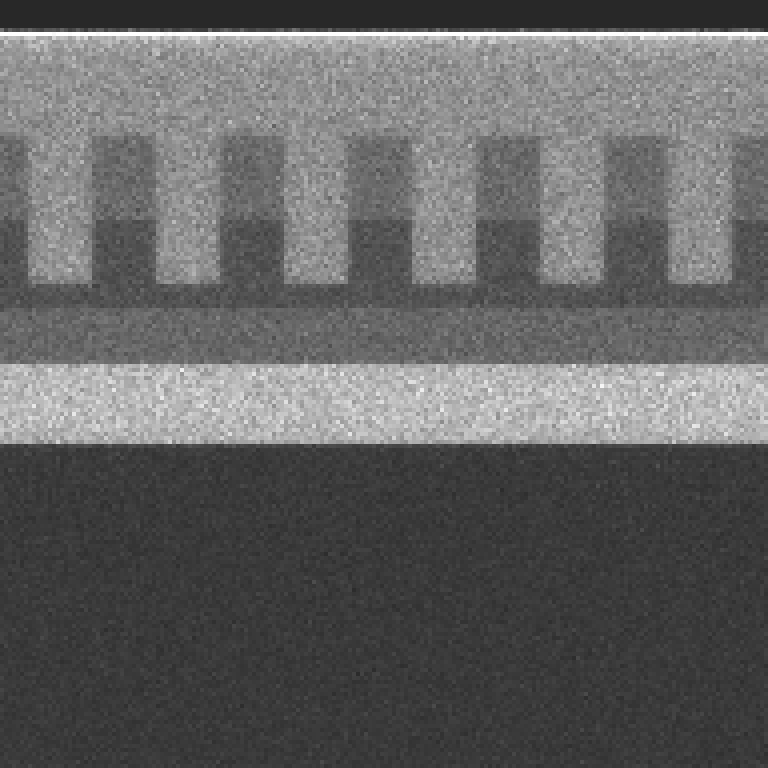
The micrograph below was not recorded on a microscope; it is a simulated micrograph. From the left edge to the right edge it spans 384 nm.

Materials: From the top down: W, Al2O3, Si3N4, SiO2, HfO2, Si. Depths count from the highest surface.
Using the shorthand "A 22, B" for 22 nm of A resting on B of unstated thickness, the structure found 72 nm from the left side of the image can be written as W 52, Al2O3 42, Si3N4 44, SiO2 28, HfO2 40, Si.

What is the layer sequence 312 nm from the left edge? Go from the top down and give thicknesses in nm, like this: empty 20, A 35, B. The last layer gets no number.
W 52, Al2O3 42, Si3N4 44, SiO2 28, HfO2 40, Si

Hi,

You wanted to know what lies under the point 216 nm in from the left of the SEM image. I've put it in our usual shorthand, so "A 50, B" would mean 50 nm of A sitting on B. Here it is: W 126, Si3N4 12, SiO2 28, HfO2 40, Si